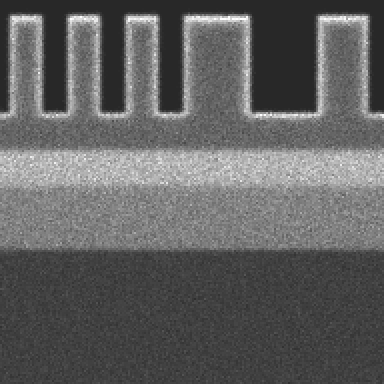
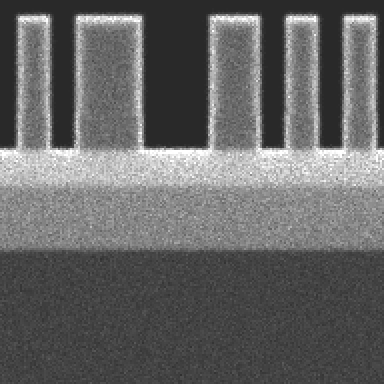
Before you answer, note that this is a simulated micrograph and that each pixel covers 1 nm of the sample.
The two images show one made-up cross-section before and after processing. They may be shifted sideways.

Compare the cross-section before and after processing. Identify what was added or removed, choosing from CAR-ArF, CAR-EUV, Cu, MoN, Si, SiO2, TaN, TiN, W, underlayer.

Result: TiN removed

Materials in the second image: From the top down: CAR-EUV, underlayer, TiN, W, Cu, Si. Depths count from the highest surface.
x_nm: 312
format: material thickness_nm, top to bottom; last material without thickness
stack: CAR-EUV 50, underlayer 48, TiN 36, W 36, Cu 64, Si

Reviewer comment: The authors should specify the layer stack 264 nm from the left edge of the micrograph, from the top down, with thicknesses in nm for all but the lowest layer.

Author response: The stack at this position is empty 134, W 36, Cu 64, Si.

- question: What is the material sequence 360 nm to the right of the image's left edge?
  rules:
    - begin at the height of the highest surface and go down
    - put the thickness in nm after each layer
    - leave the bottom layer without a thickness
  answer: CAR-EUV 50, underlayer 48, TiN 36, W 36, Cu 64, Si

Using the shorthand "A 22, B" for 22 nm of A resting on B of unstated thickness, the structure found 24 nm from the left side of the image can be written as CAR-EUV 50, underlayer 48, TiN 36, W 36, Cu 64, Si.